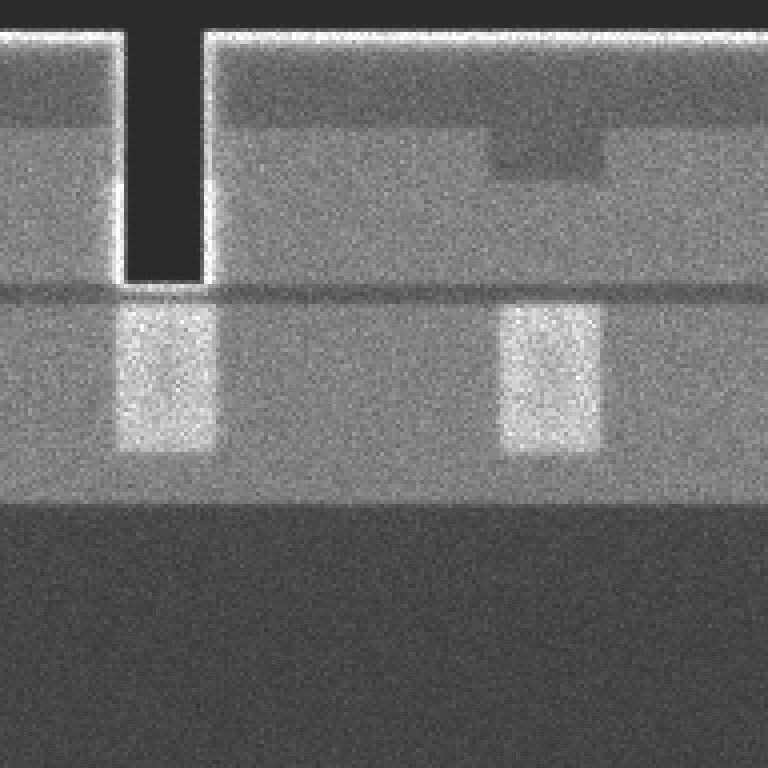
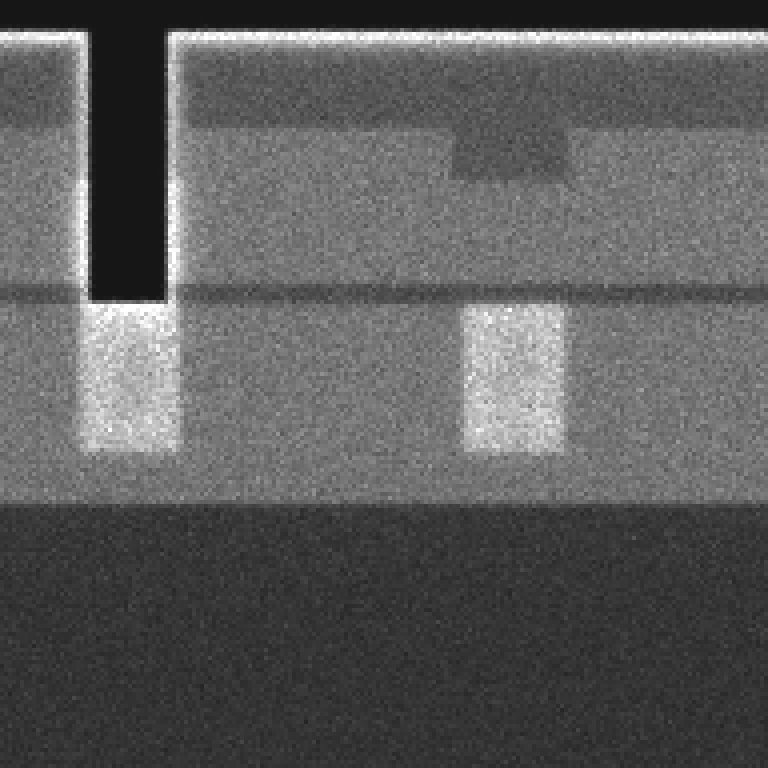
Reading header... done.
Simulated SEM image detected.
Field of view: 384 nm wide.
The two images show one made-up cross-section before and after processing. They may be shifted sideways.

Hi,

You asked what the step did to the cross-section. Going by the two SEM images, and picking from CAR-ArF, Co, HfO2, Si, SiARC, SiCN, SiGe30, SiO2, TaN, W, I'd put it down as SiCN, removed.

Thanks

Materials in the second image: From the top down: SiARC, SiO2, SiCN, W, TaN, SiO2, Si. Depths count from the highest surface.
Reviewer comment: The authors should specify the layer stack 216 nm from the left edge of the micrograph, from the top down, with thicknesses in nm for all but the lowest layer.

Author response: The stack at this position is SiARC 48, SiO2 78, SiCN 10, SiO2 100, Si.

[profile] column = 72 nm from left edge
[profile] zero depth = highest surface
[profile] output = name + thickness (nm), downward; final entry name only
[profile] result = empty 136, W 66, TaN 8, SiO2 26, Si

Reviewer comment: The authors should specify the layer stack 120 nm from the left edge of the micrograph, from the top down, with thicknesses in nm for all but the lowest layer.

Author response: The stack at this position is SiARC 48, SiO2 78, SiCN 10, SiO2 100, Si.